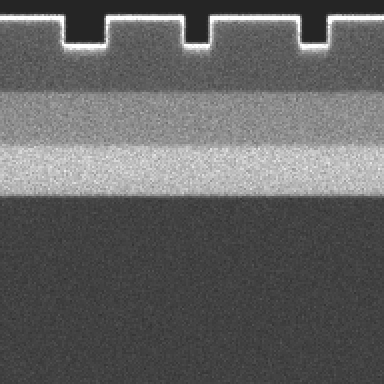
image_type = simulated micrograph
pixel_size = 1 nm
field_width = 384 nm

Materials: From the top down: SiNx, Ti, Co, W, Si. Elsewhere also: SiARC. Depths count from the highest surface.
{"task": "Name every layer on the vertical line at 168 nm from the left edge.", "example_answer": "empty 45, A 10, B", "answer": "SiNx 8, Ti 68, Co 54, W 50, Si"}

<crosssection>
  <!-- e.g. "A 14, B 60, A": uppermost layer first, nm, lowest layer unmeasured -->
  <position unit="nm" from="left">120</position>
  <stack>SiNx 8, Ti 68, Co 54, W 50, Si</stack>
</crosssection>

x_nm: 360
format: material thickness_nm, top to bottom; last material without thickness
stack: SiNx 8, Ti 68, Co 54, W 50, Si